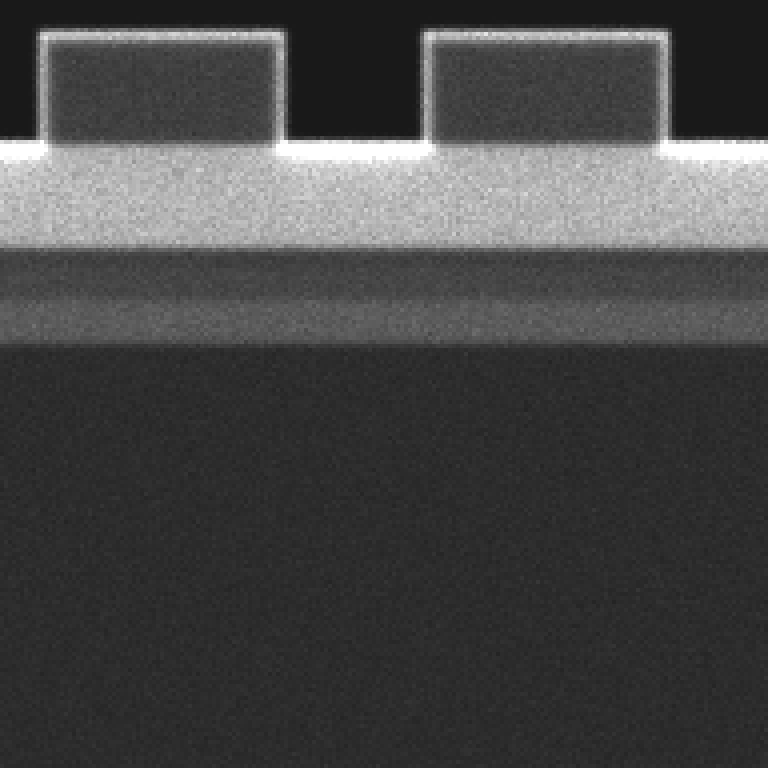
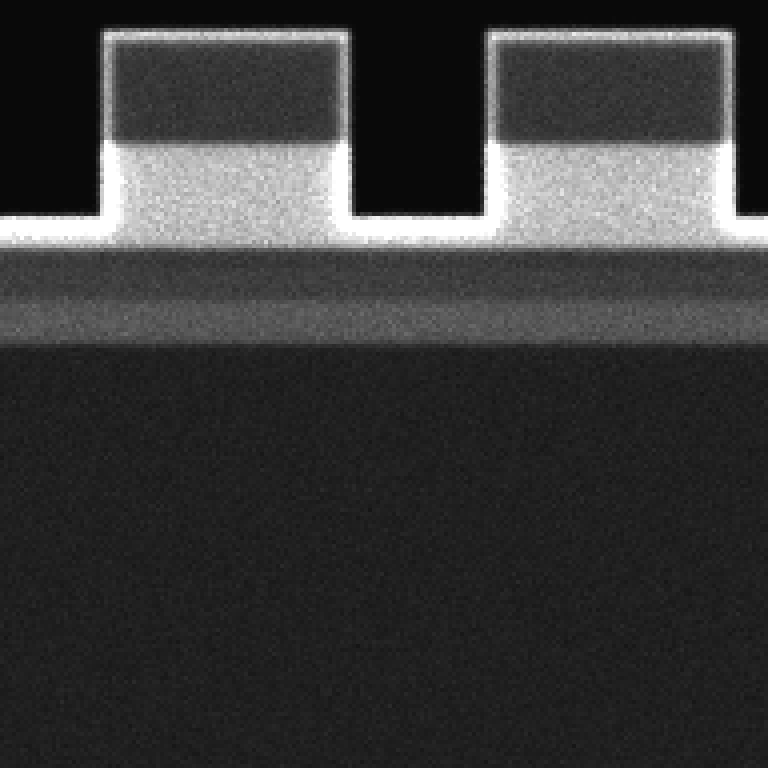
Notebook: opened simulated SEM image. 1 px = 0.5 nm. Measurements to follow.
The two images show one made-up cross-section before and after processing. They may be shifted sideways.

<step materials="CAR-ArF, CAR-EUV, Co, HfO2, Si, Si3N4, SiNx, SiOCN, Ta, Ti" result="removed HfO2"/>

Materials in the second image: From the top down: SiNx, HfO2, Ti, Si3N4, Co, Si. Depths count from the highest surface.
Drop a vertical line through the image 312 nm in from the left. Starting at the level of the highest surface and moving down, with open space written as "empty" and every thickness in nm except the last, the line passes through SiNx 56, HfO2 52, Ti 10, Si3N4 16, Co 22, Si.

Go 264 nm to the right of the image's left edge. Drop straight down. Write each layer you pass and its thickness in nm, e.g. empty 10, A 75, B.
SiNx 56, HfO2 52, Ti 10, Si3N4 16, Co 22, Si